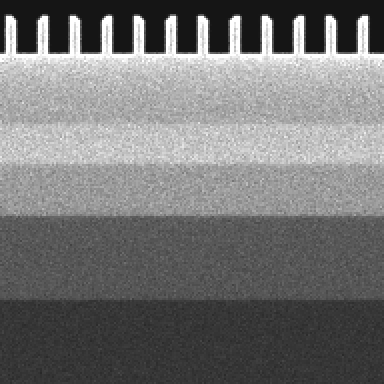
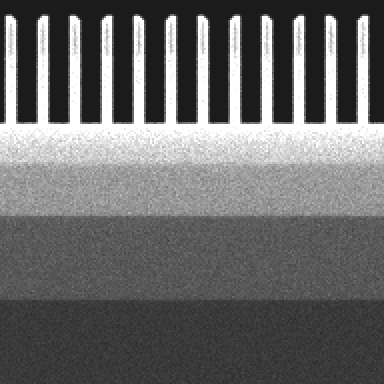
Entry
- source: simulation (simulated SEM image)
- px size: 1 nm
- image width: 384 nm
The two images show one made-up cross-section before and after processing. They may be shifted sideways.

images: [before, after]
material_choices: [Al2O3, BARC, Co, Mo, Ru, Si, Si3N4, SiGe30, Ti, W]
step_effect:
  removed: Ru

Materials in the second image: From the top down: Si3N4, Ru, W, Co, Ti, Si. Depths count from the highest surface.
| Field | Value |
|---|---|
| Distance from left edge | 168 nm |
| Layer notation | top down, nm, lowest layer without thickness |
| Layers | empty 2, Si3N4 36, Ru 70, W 40, Co 52, Ti 84, Si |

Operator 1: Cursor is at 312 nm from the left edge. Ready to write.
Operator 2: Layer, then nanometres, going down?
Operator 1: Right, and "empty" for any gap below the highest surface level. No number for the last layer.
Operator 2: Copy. empty 108, W 40, Co 52, Ti 84, Si